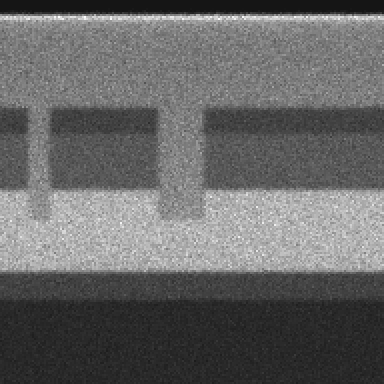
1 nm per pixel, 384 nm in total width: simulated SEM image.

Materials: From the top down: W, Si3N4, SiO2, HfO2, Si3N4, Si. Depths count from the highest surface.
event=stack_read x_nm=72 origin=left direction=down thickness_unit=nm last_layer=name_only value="W 92, Si3N4 26, SiO2 56, HfO2 82, Si3N4 28, Si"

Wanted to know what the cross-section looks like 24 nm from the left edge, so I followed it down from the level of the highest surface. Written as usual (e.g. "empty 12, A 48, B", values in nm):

W 92, Si3N4 26, SiO2 56, HfO2 82, Si3N4 28, Si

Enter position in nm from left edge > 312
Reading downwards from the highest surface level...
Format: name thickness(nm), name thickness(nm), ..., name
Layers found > W 92, Si3N4 26, SiO2 56, HfO2 82, Si3N4 28, Si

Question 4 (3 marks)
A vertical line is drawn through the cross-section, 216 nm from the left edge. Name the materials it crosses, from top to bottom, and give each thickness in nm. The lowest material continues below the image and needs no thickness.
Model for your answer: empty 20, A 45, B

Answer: W 92, Si3N4 26, SiO2 56, HfO2 82, Si3N4 28, Si